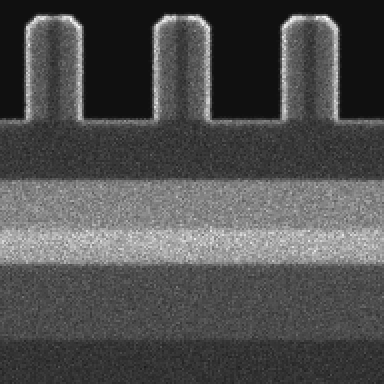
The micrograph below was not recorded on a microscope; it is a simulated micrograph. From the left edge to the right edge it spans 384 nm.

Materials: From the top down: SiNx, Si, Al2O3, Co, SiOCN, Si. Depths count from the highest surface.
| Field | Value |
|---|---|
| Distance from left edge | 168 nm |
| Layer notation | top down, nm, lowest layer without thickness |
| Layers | SiNx 104, Si 60, Al2O3 50, Co 34, SiOCN 76, Si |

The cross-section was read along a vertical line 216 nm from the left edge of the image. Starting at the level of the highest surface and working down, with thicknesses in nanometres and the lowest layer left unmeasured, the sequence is empty 104, Si 60, Al2O3 50, Co 34, SiOCN 76, Si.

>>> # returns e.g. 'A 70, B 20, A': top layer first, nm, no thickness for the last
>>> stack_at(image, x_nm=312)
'Si 164, Al2O3 50, Co 34, SiOCN 76, Si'